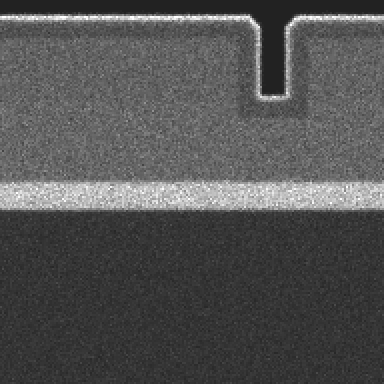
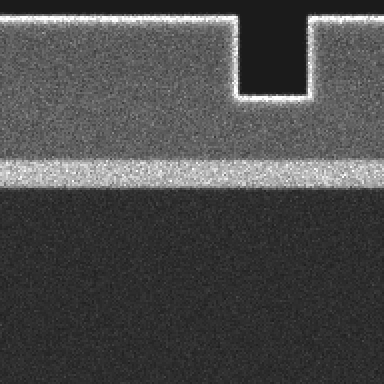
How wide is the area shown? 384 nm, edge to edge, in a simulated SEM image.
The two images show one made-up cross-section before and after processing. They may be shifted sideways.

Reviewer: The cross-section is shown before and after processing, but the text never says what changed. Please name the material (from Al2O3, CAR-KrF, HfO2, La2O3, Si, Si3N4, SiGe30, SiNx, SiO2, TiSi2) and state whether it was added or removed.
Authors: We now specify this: Si3N4, removed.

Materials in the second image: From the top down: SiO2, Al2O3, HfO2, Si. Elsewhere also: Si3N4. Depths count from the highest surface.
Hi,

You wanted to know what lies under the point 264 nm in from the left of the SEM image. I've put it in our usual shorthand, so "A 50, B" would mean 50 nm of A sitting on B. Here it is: empty 80, Al2O3 64, HfO2 28, Si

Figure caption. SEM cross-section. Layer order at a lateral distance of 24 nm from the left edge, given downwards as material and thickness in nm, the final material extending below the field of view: SiO2 64, Al2O3 80, HfO2 28, Si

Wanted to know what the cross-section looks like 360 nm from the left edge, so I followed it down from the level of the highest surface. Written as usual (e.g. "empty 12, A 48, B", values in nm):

SiO2 64, Al2O3 80, HfO2 28, Si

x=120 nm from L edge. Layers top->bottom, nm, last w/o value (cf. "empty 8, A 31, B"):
SiO2 64, Al2O3 80, HfO2 28, Si